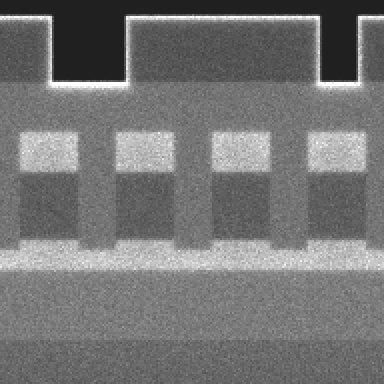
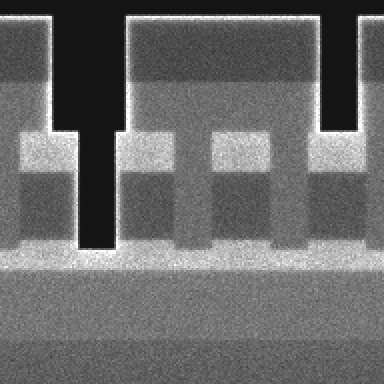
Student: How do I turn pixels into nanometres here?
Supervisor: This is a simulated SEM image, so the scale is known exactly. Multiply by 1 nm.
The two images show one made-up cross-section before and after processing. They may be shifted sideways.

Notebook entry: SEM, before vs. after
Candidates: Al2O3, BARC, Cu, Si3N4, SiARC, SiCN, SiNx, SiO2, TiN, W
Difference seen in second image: SiO2 removed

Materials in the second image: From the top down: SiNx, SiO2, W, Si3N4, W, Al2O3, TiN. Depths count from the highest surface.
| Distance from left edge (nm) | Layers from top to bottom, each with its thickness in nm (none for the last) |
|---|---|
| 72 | empty 116, W 40, Si3N4 68, W 30, Al2O3 70, TiN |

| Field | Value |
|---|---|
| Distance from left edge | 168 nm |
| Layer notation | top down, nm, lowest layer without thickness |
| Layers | SiNx 66, SiO2 50, W 40, Si3N4 68, W 30, Al2O3 70, TiN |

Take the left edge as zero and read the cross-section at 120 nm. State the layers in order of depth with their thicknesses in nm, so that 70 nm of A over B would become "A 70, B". empty 116, W 40, Si3N4 68, W 30, Al2O3 70, TiN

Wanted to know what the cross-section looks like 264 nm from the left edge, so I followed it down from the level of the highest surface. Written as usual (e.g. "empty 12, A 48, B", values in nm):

SiNx 66, SiO2 50, W 40, Si3N4 68, W 30, Al2O3 70, TiN